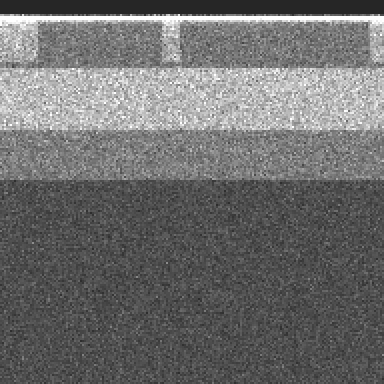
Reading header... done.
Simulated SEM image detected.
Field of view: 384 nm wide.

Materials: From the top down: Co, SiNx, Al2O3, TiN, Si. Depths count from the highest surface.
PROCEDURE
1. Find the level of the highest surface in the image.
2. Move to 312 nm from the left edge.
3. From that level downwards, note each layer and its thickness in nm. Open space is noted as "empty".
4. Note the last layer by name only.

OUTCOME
SiNx 52, Al2O3 62, TiN 50, Si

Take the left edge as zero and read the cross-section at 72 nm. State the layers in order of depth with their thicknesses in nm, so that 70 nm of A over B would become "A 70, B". SiNx 52, Al2O3 62, TiN 50, Si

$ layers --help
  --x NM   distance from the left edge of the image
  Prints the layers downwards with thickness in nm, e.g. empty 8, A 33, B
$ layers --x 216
SiNx 52, Al2O3 62, TiN 50, Si